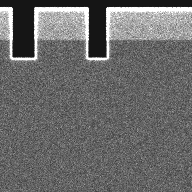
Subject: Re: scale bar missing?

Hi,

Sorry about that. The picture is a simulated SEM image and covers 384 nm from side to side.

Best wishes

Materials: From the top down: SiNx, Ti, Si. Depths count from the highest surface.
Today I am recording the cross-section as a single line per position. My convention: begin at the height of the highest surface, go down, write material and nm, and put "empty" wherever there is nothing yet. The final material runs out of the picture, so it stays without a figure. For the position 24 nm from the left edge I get empty 100, Si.